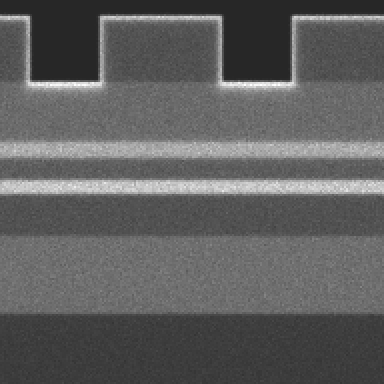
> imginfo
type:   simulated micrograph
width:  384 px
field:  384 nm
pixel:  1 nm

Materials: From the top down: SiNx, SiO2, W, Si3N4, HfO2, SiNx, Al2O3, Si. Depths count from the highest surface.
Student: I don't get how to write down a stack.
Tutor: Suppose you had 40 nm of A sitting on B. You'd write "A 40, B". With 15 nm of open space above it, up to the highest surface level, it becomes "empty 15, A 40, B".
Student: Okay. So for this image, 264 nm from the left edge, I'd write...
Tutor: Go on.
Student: empty 66, SiO2 60, W 16, Si3N4 22, HfO2 14, SiNx 42, Al2O3 78, Si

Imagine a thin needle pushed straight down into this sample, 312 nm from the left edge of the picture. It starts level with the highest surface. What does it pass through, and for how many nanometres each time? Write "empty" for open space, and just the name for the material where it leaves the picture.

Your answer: SiNx 66, SiO2 60, W 16, Si3N4 22, HfO2 14, SiNx 42, Al2O3 78, Si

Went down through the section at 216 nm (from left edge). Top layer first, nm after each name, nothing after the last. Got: SiNx 66, SiO2 60, W 16, Si3N4 22, HfO2 14, SiNx 42, Al2O3 78, Si